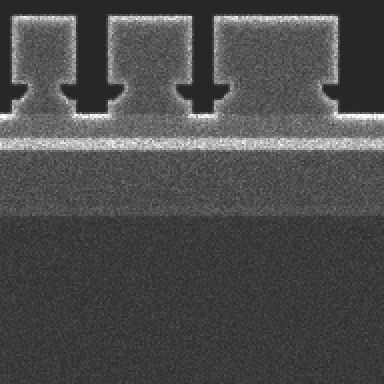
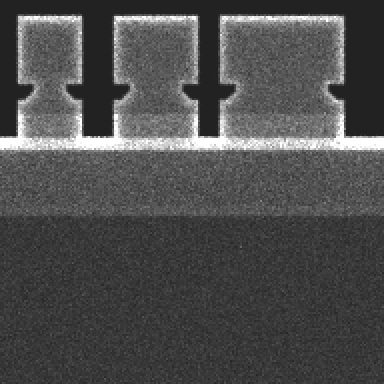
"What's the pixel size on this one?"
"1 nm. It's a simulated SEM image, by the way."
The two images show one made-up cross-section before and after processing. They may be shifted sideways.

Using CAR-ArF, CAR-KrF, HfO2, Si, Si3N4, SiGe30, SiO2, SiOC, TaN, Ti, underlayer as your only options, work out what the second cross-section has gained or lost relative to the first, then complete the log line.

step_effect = removed SiO2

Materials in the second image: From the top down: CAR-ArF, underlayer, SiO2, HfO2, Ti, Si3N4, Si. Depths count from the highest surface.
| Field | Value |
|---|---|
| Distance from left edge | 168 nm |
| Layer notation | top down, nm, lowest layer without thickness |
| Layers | CAR-ArF 68, underlayer 30, SiO2 24, HfO2 12, Ti 56, Si3N4 10, Si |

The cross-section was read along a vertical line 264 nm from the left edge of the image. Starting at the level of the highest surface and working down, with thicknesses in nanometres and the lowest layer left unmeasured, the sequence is CAR-ArF 68, underlayer 30, SiO2 24, HfO2 12, Ti 56, Si3N4 10, Si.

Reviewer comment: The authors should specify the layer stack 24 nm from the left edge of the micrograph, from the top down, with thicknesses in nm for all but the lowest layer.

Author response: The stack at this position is CAR-ArF 68, empty 16, underlayer 14, SiO2 24, HfO2 12, Ti 56, Si3N4 10, Si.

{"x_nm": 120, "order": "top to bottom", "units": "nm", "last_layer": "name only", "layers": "CAR-ArF 68, empty 16, underlayer 14, SiO2 24, HfO2 12, Ti 56, Si3N4 10, Si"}